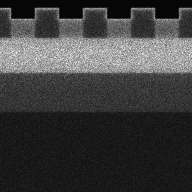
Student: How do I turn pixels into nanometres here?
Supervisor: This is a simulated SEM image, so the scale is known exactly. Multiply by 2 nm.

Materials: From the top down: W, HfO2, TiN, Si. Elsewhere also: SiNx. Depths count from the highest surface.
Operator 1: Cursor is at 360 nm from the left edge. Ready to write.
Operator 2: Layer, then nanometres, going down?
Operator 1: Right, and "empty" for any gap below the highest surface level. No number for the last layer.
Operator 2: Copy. SiNx 60, HfO2 70, TiN 78, Si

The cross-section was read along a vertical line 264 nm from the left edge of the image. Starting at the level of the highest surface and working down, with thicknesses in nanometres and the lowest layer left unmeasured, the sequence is SiNx 60, HfO2 70, TiN 78, Si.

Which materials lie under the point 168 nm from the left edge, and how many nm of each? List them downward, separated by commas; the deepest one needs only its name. SiNx 60, HfO2 70, TiN 78, Si